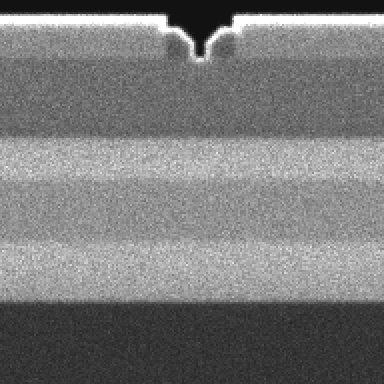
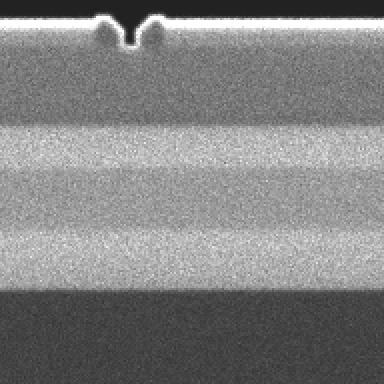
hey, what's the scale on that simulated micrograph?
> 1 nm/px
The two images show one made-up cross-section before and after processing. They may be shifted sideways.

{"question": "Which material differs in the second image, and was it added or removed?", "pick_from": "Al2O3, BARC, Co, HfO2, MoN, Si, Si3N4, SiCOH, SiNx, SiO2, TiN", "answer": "SiO2, removed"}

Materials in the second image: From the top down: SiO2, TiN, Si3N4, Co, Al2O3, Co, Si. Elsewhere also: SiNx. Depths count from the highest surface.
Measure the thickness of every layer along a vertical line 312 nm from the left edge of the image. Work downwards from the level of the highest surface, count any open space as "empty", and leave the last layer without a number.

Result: empty 4, SiO2 26, TiN 68, Si3N4 12, Co 42, Al2O3 62, Co 60, Si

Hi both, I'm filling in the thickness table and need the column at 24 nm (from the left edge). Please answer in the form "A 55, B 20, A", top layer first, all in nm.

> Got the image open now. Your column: empty 4, SiO2 26, TiN 68, Si3N4 12, Co 42, Al2O3 62, Co 60, Si